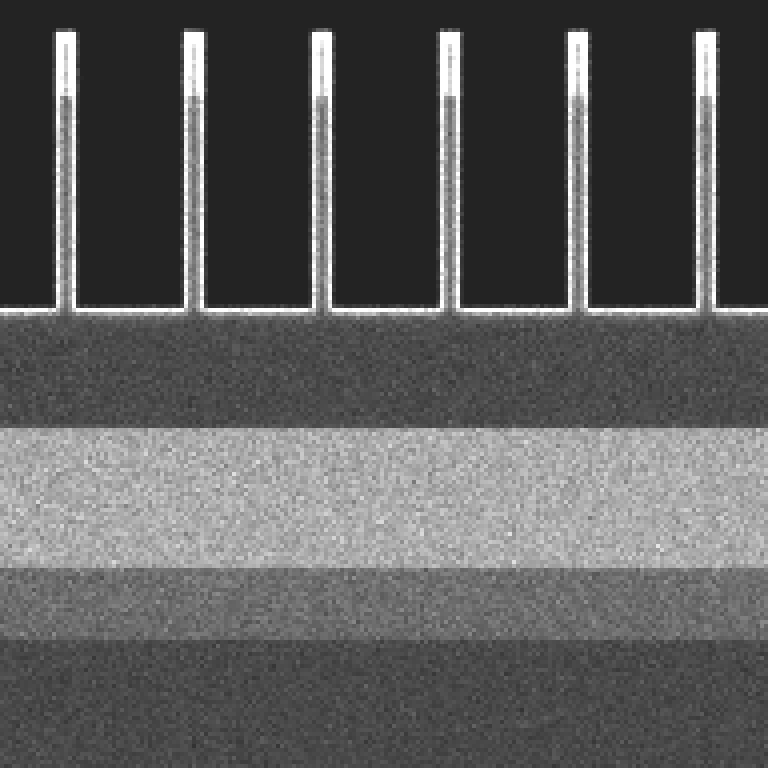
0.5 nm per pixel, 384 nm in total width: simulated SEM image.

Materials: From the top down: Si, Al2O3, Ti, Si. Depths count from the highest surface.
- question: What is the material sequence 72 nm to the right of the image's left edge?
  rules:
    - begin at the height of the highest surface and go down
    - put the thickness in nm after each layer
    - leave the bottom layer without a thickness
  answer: empty 138, Si 60, Al2O3 70, Ti 36, Si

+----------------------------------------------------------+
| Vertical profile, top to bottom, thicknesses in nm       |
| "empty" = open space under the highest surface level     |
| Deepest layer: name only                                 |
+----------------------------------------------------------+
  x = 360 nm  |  empty 138, Si 60, Al2O3 70, Ti 36, Si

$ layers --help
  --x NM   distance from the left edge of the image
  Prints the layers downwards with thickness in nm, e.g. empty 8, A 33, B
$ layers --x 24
empty 138, Si 60, Al2O3 70, Ti 36, Si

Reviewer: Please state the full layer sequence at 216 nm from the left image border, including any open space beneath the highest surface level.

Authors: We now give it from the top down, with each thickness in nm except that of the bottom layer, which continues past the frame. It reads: empty 138, Si 60, Al2O3 70, Ti 36, Si